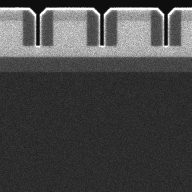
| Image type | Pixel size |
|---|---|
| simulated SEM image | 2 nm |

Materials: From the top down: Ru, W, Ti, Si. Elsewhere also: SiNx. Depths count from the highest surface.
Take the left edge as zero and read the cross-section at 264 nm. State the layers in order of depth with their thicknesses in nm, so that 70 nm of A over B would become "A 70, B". Ru 26, W 72, Ti 30, Si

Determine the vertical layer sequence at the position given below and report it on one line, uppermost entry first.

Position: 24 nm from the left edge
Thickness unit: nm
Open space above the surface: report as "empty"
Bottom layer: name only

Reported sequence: Ru 26, W 72, Ti 30, Si